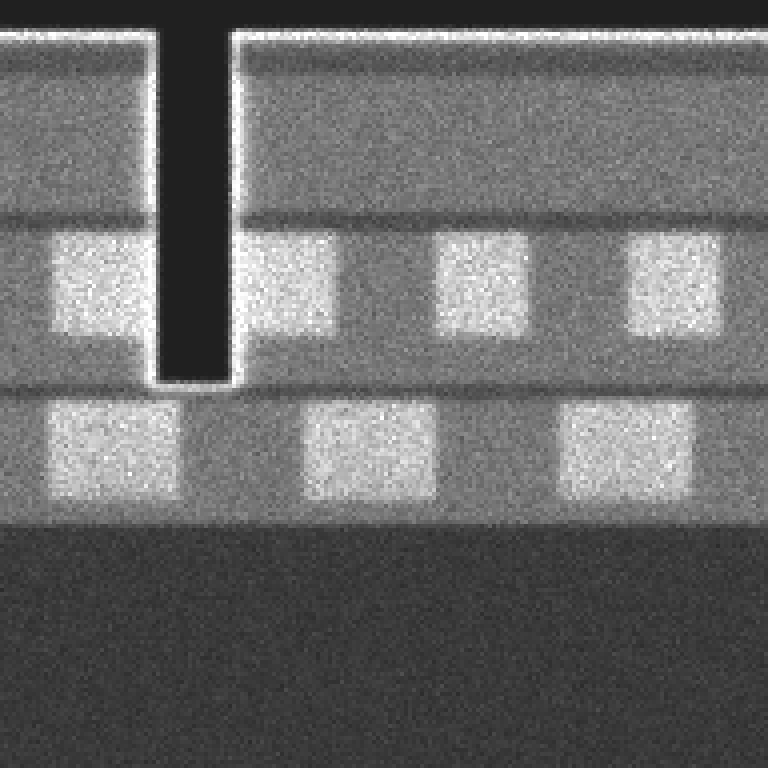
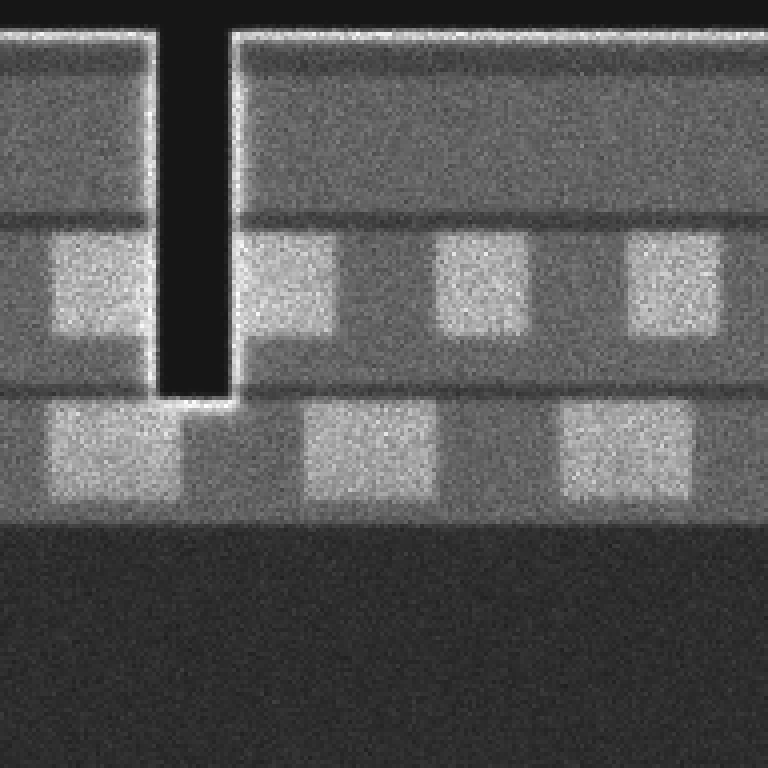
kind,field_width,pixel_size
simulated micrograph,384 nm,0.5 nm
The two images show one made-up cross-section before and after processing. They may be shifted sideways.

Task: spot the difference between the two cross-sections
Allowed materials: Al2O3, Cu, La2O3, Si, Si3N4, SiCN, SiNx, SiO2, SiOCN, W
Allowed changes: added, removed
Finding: removed SiCN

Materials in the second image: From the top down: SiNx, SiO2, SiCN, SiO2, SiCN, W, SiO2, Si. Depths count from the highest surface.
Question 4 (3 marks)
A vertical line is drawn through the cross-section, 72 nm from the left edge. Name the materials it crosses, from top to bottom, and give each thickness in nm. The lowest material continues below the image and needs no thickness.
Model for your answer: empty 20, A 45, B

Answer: SiNx 22, SiO2 68, SiCN 10, SiO2 76, SiCN 8, W 50, SiO2 12, Si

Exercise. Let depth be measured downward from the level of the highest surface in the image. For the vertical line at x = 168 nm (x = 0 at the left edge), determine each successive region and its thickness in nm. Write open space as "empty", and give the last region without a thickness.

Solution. SiNx 22, SiO2 68, SiCN 10, SiO2 76, SiCN 8, W 50, SiO2 12, Si